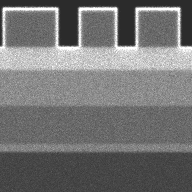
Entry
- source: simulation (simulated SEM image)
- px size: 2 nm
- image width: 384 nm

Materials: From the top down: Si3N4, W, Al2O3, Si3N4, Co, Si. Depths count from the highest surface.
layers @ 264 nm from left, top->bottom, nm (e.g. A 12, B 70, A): empty 78, W 46, Al2O3 72, Si3N4 76, Co 16, Si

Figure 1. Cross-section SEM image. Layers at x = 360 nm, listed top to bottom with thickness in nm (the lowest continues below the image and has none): empty 78, W 46, Al2O3 72, Si3N4 76, Co 16, Si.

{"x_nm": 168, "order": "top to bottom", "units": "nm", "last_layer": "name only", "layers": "Si3N4 78, W 46, Al2O3 72, Si3N4 76, Co 16, Si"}